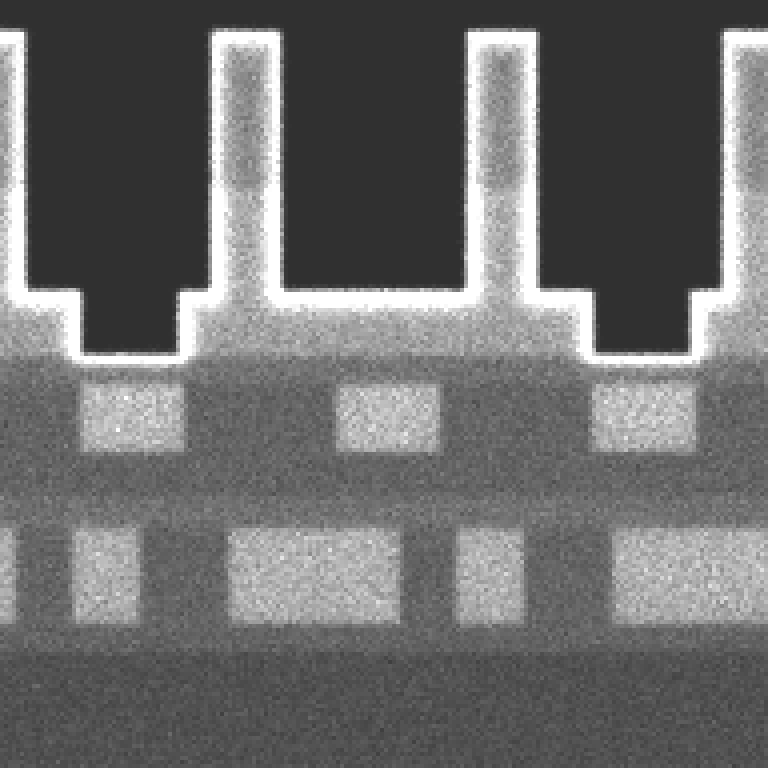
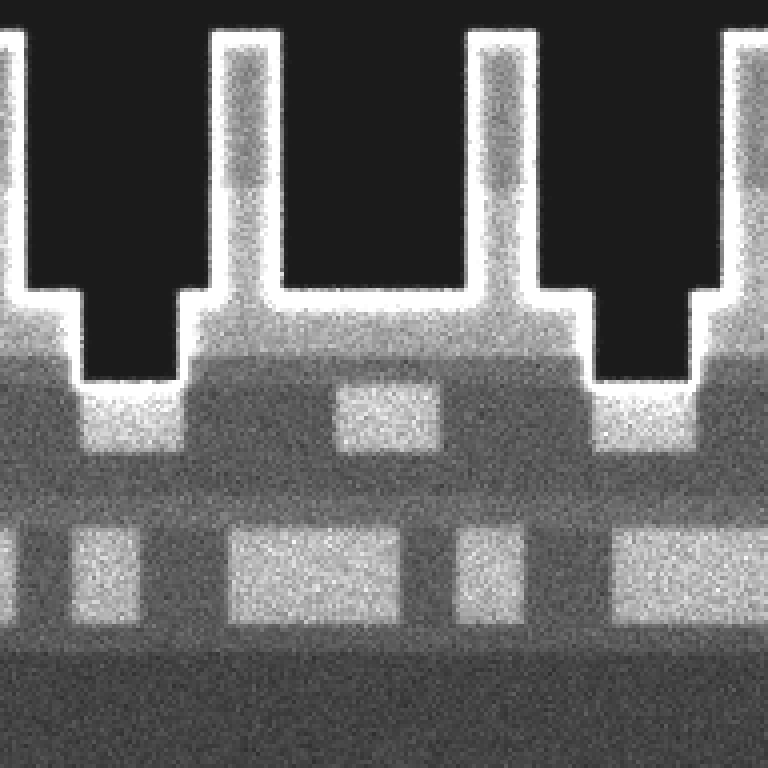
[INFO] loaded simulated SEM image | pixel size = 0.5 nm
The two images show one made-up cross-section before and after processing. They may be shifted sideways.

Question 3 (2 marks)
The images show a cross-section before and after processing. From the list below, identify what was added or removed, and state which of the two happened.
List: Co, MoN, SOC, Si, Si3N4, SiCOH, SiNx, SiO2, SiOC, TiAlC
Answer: SiNx was removed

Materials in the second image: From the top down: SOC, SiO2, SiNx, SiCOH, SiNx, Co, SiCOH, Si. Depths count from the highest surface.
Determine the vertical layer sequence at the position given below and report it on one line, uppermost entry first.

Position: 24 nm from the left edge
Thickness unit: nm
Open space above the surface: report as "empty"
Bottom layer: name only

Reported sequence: empty 130, SiO2 32, SiNx 14, SiCOH 56, SiNx 16, SiCOH 62, Si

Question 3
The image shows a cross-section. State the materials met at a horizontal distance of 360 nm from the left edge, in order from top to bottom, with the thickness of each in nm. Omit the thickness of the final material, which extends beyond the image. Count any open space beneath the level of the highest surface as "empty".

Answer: empty 130, SiO2 32, SiNx 14, SiCOH 56, SiNx 16, Co 48, SiCOH 14, Si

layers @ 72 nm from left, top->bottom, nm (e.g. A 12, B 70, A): empty 176, Co 34, SiCOH 22, SiNx 16, SiCOH 62, Si